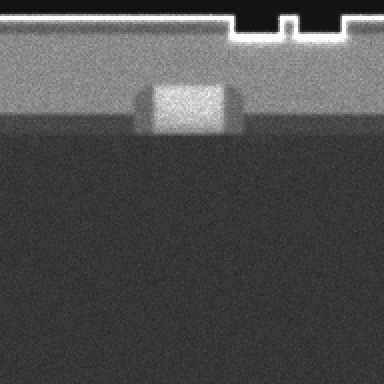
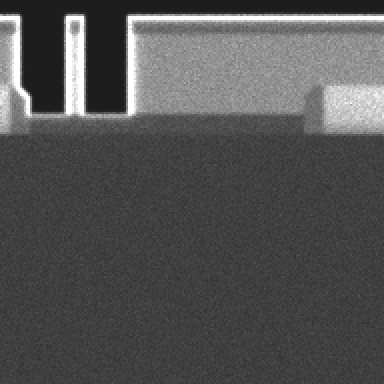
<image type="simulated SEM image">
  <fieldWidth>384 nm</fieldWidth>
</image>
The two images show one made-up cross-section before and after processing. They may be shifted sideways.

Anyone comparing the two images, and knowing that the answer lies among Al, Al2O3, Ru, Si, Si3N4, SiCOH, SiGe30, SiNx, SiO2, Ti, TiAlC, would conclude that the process removed SiO2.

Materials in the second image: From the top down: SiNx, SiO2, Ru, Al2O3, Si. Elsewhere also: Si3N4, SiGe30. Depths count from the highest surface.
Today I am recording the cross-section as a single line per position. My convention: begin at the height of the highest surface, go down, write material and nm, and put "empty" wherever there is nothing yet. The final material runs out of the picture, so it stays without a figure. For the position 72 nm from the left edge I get SiNx 18, SiO2 80, SiGe30 20, Si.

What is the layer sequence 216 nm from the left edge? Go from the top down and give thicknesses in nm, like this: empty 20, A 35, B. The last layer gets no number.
SiNx 18, SiO2 80, SiGe30 20, Si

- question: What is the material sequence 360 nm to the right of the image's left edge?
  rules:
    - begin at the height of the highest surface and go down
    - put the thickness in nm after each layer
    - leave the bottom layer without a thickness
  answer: SiNx 18, SiO2 52, Ru 40, Al2O3 8, Si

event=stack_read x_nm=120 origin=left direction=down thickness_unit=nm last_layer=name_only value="empty 98, SiGe30 20, Si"